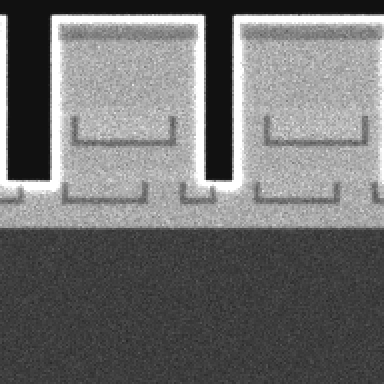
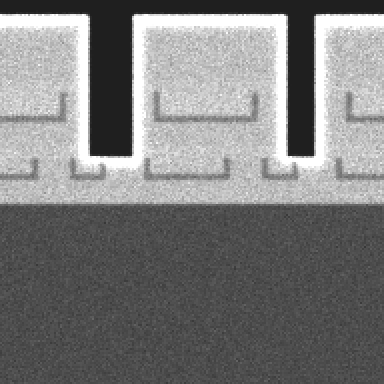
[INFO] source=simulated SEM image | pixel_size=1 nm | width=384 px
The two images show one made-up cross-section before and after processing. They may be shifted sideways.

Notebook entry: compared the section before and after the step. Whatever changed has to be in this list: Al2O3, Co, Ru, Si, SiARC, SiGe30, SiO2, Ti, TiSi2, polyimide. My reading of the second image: SiARC removed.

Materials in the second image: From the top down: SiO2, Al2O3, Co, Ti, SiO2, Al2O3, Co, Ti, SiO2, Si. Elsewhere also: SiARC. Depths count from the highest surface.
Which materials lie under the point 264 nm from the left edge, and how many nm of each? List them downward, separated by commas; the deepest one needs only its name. SiO2 66, Al2O3 10, SiO2 54, Al2O3 12, Ti 22, SiO2 24, Si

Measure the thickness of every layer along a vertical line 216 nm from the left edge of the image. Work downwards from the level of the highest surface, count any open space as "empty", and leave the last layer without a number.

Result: SiO2 66, Al2O3 10, Co 24, Ti 6, SiO2 24, Al2O3 12, Co 16, Ti 6, SiO2 24, Si